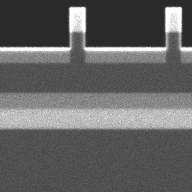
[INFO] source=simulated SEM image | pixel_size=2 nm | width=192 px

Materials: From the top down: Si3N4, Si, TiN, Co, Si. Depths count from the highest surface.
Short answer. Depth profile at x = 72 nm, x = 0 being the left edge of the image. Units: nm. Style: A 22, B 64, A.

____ empty 80, Si3N4 30, Si 60, TiN 32, Co 40, Si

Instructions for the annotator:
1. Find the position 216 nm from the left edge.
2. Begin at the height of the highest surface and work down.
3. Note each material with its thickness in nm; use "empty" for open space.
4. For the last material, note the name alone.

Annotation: empty 80, Si3N4 30, Si 60, TiN 32, Co 40, Si